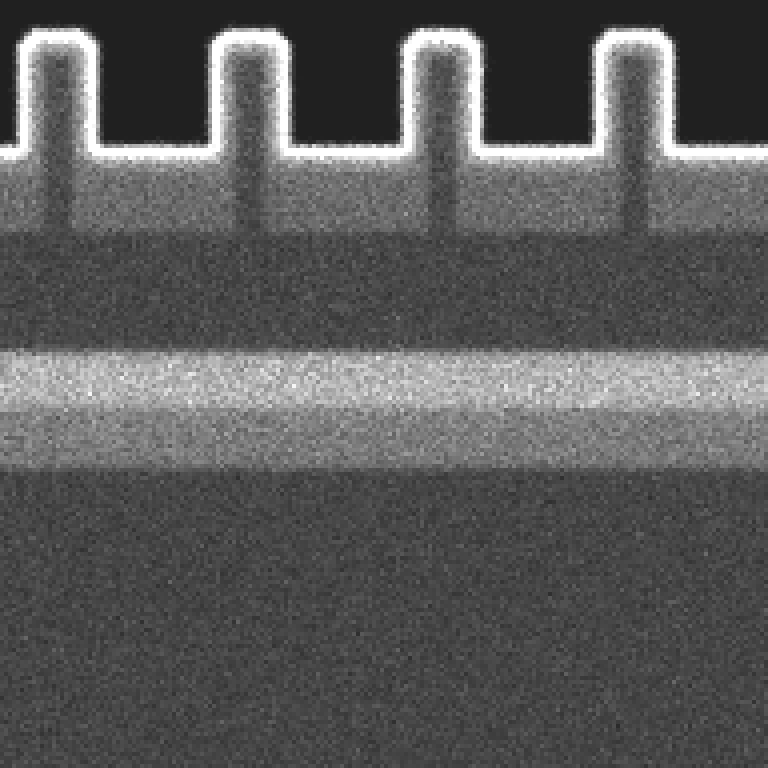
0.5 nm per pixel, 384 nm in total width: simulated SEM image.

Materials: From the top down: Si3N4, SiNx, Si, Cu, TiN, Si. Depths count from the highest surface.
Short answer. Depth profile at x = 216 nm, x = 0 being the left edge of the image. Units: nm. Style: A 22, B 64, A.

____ Si3N4 12, Si 148, Cu 28, TiN 30, Si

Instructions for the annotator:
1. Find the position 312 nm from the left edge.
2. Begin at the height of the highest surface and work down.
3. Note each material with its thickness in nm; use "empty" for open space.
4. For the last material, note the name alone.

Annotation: Si3N4 12, Si 148, Cu 28, TiN 30, Si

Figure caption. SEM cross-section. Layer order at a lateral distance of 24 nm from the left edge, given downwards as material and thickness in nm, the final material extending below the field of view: Si3N4 12, Si 148, Cu 28, TiN 30, Si